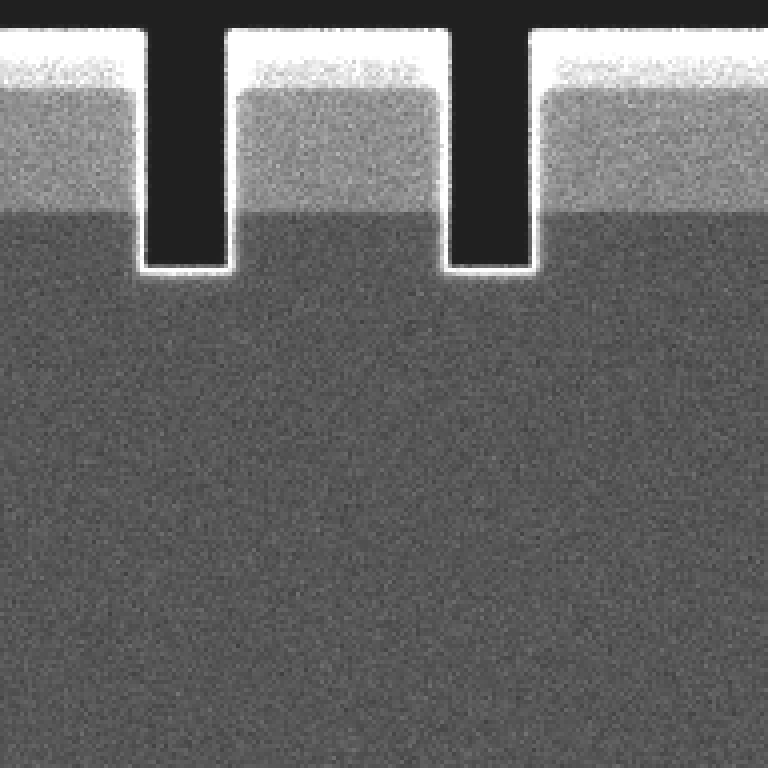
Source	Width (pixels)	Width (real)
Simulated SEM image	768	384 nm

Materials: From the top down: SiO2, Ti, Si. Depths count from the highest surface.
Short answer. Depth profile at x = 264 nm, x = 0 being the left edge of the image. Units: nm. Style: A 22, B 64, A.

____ empty 118, Si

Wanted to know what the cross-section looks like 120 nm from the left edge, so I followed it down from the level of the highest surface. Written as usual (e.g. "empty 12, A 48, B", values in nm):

SiO2 28, Ti 62, Si